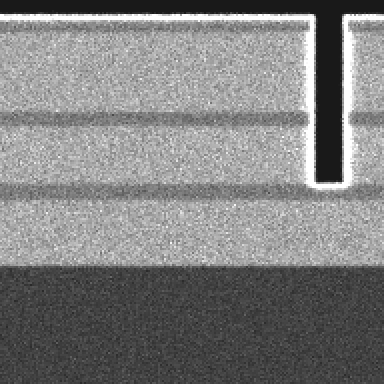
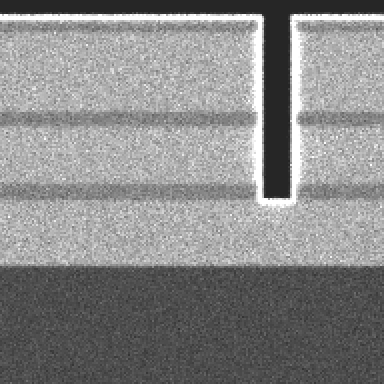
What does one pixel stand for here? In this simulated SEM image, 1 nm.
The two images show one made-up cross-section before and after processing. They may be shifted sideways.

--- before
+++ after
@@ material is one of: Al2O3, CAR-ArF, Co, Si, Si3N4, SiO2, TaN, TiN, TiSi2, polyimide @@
Si3N4 removed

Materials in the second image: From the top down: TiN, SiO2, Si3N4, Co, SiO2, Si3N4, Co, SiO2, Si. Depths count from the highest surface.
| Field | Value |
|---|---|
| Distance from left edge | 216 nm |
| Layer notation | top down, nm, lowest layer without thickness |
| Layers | TiN 16, SiO2 80, Si3N4 14, SiO2 58, Si3N4 16, SiO2 66, Si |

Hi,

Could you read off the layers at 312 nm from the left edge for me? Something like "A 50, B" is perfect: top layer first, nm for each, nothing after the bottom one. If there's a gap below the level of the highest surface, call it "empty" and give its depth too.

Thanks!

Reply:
TiN 16, SiO2 80, Si3N4 14, Co 36, SiO2 22, Si3N4 16, Co 48, SiO2 18, Si